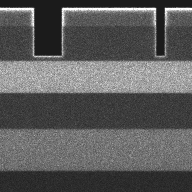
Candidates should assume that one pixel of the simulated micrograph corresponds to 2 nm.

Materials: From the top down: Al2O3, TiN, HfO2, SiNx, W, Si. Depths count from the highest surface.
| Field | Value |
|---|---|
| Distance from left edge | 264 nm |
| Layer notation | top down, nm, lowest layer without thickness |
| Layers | Al2O3 36, TiN 70, HfO2 64, SiNx 72, W 84, Si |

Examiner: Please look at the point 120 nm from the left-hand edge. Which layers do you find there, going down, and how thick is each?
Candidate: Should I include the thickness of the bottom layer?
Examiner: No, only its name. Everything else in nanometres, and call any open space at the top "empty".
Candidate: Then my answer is empty 96, TiN 10, HfO2 64, SiNx 72, W 84, Si